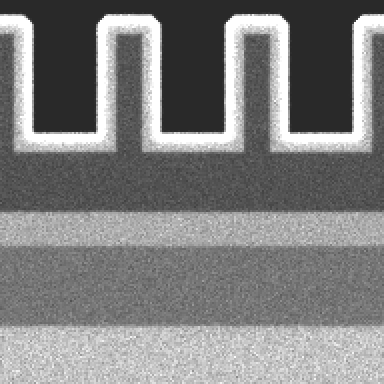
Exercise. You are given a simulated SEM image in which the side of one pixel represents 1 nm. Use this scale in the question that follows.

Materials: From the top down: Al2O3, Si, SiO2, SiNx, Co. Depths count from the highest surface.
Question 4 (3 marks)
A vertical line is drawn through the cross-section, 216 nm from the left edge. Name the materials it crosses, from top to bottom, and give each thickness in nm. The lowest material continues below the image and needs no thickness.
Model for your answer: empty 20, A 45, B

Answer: empty 118, Al2O3 18, Si 60, SiO2 34, SiNx 80, Co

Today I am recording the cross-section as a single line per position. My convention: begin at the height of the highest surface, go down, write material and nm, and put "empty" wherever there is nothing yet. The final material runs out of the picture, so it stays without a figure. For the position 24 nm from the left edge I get empty 2, Al2O3 134, Si 60, SiO2 34, SiNx 80, Co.